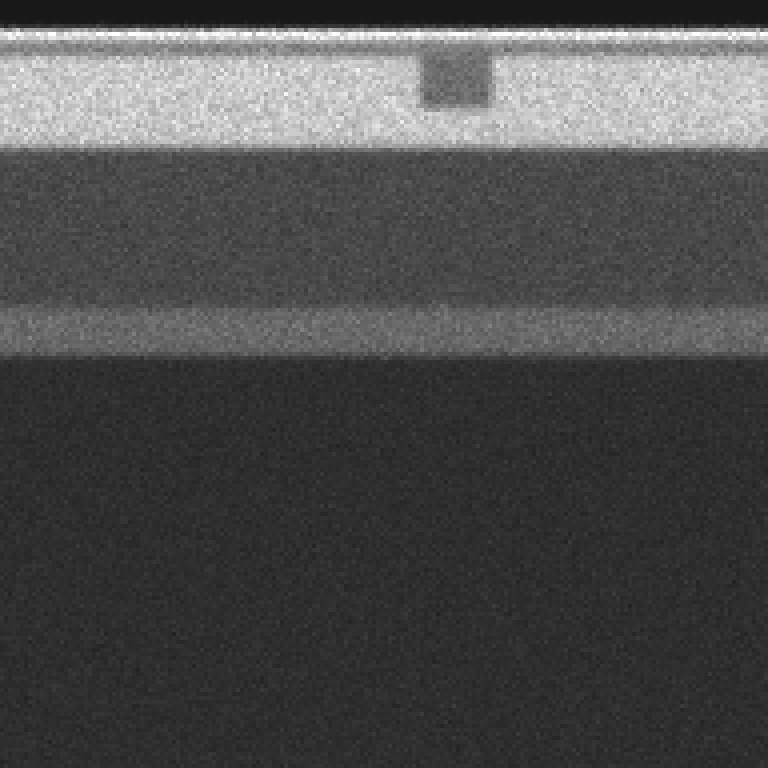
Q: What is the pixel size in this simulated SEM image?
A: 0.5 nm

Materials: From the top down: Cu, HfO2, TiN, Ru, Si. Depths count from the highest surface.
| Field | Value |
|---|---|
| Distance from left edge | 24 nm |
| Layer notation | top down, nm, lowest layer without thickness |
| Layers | Cu 12, HfO2 46, TiN 80, Ru 24, Si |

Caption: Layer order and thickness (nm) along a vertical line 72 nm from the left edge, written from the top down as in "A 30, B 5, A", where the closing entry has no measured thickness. Cu 12, HfO2 46, TiN 80, Ru 24, Si